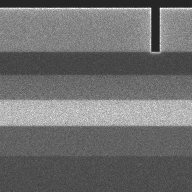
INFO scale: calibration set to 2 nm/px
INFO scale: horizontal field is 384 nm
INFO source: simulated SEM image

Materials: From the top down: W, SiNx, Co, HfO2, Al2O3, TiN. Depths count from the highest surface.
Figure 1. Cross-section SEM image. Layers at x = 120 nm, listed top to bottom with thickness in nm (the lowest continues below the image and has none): W 88, SiNx 46, Co 50, HfO2 52, Al2O3 60, TiN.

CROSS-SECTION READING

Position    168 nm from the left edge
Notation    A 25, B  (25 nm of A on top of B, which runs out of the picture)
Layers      W 88, SiNx 46, Co 50, HfO2 52, Al2O3 60, TiN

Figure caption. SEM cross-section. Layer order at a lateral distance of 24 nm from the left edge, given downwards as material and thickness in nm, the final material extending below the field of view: W 88, SiNx 46, Co 50, HfO2 52, Al2O3 60, TiN